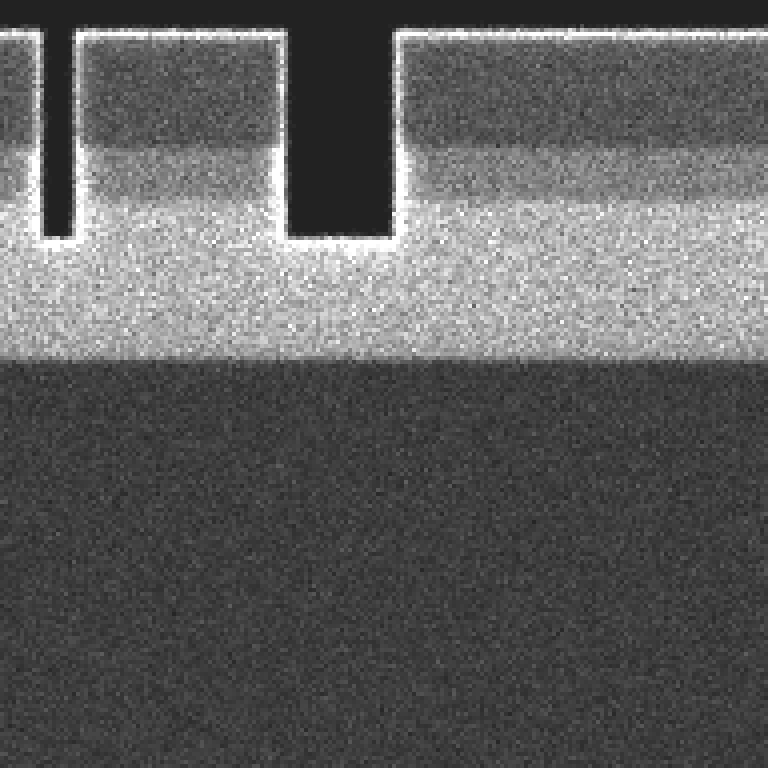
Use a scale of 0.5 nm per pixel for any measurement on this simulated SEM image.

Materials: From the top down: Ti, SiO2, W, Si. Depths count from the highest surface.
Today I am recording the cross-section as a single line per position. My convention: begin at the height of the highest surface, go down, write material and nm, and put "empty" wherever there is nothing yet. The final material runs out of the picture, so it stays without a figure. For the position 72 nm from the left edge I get Ti 58, SiO2 26, W 80, Si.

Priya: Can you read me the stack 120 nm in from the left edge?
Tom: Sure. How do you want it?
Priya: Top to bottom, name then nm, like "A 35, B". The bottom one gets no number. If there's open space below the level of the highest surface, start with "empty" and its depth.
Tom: Ti 58, SiO2 26, W 80, Si